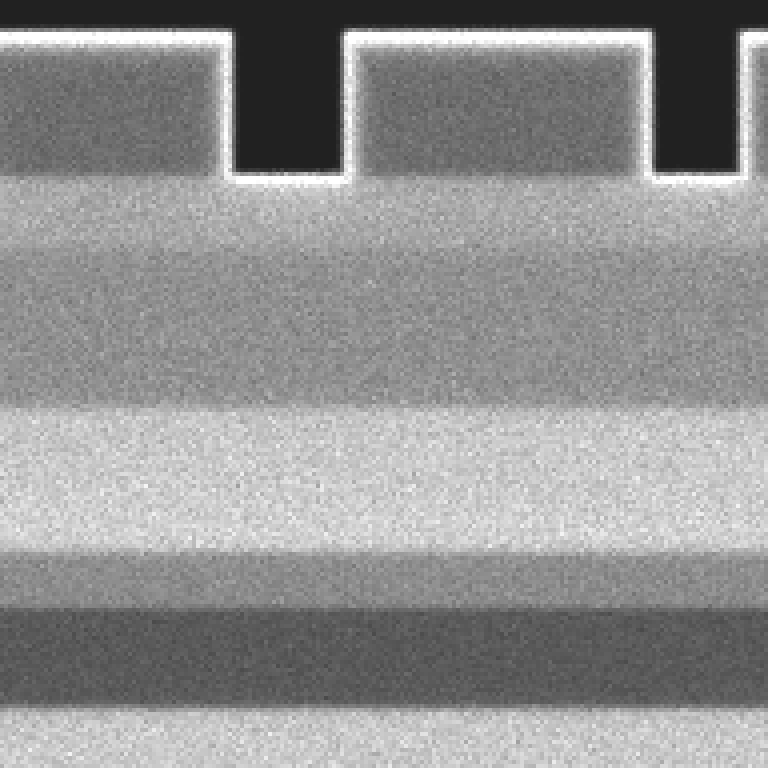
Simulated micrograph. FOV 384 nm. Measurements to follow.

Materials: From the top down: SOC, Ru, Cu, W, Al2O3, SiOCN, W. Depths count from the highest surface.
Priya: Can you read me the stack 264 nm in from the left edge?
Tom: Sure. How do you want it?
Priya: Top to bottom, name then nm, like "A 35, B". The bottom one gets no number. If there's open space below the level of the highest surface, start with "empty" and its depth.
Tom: SOC 72, Ru 36, Cu 80, W 72, Al2O3 28, SiOCN 50, W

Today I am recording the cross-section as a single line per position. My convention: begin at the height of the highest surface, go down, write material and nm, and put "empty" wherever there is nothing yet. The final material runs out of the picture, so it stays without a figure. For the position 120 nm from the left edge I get empty 72, Ru 36, Cu 80, W 72, Al2O3 28, SiOCN 50, W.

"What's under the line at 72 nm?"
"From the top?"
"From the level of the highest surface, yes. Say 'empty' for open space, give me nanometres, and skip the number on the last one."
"SOC 72, Ru 36, Cu 80, W 72, Al2O3 28, SiOCN 50, W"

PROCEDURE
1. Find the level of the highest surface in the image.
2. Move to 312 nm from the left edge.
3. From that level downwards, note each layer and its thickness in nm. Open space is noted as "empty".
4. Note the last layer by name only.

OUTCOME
SOC 72, Ru 36, Cu 80, W 72, Al2O3 28, SiOCN 50, W